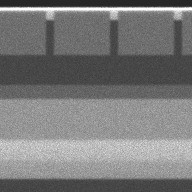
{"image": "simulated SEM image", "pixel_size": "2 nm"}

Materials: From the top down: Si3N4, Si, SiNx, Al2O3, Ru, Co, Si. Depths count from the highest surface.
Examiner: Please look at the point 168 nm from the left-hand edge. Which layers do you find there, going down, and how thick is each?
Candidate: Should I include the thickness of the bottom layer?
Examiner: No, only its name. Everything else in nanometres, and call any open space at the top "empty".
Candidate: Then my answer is Si3N4 94, Si 60, SiNx 28, Al2O3 82, Ru 42, Co 36, Si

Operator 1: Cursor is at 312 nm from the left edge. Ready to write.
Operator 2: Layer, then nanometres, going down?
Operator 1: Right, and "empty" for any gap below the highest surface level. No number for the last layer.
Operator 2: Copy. Si3N4 94, Si 60, SiNx 28, Al2O3 82, Ru 42, Co 36, Si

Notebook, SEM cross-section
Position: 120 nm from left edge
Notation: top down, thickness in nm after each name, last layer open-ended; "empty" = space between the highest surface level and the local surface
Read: Si3N4 94, Si 60, SiNx 28, Al2O3 82, Ru 42, Co 36, Si